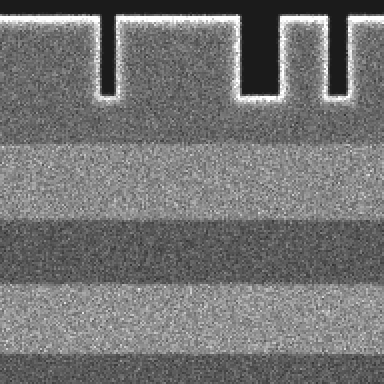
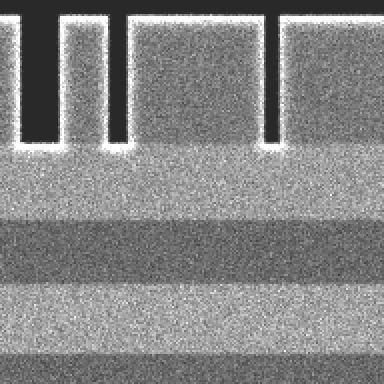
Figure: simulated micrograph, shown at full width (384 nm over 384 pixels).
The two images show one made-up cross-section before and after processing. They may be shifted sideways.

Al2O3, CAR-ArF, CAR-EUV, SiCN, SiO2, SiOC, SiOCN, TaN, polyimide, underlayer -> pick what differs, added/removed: underlayer removed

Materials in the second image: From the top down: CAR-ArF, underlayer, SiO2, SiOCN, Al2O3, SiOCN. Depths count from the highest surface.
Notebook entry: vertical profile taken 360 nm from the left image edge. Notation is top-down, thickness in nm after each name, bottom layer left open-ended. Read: CAR-ArF 80, underlayer 48, SiO2 76, SiOCN 64, Al2O3 70, SiOCN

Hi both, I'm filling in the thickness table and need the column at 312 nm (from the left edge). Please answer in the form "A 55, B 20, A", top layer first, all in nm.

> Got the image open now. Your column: CAR-ArF 80, underlayer 48, SiO2 76, SiOCN 64, Al2O3 70, SiOCN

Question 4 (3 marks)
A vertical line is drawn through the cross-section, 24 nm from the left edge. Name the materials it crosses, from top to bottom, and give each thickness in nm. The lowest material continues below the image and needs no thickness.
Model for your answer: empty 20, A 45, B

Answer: empty 128, SiO2 76, SiOCN 64, Al2O3 70, SiOCN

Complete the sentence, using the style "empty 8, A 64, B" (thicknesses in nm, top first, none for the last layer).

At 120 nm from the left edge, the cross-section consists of empty 128, SiO2 76, SiOCN 64, Al2O3 70, SiOCN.